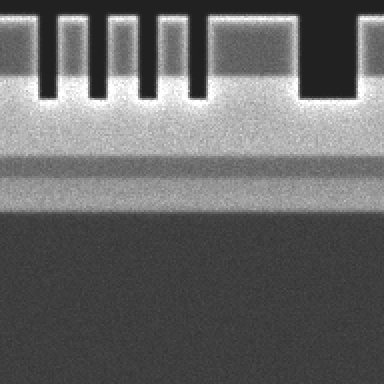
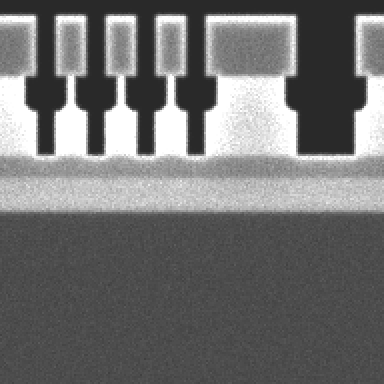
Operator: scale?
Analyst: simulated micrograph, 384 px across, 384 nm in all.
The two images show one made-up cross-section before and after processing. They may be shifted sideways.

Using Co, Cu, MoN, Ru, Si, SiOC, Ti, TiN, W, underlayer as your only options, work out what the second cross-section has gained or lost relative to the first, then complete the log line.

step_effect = removed W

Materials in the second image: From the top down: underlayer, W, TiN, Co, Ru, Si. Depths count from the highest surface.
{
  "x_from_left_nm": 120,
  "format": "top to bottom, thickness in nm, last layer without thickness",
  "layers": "underlayer 60, W 80, TiN 22, Co 18, Ru 16, Si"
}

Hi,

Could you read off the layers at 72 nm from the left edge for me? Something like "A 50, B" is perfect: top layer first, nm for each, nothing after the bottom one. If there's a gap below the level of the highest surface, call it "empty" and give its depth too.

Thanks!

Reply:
underlayer 60, W 80, TiN 22, Co 18, Ru 16, Si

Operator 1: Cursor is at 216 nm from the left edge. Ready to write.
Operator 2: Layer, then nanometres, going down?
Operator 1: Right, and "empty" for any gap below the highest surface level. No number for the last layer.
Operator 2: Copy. underlayer 60, empty 30, W 50, TiN 22, Co 18, Ru 16, Si